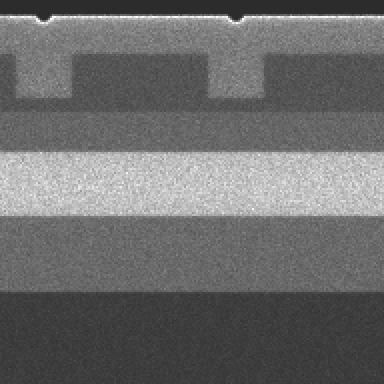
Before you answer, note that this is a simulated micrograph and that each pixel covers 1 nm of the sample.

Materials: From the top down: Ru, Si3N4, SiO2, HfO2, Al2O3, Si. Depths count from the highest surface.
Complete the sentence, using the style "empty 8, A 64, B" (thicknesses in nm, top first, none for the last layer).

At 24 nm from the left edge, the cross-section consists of Ru 82, Si3N4 14, SiO2 40, HfO2 64, Al2O3 76, Si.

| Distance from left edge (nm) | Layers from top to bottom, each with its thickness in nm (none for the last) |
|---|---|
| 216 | Ru 82, Si3N4 14, SiO2 40, HfO2 64, Al2O3 76, Si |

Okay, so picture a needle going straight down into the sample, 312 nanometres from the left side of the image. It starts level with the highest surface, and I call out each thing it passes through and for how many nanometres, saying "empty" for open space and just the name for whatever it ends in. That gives Ru 38, Si3N4 58, SiO2 40, HfO2 64, Al2O3 76, Si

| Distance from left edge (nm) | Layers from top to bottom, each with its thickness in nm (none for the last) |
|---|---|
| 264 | Ru 38, Si3N4 58, SiO2 40, HfO2 64, Al2O3 76, Si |